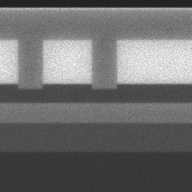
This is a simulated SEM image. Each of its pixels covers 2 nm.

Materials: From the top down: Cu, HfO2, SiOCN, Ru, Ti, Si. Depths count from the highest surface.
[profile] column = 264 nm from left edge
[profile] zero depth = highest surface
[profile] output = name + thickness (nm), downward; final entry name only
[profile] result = Cu 64, HfO2 88, SiOCN 38, Ru 40, Ti 58, Si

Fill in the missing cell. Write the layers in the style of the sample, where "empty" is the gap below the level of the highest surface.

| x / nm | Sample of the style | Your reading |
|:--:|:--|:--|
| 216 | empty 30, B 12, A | Cu 162, SiOCN 28, Ru 40, Ti 58, Si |